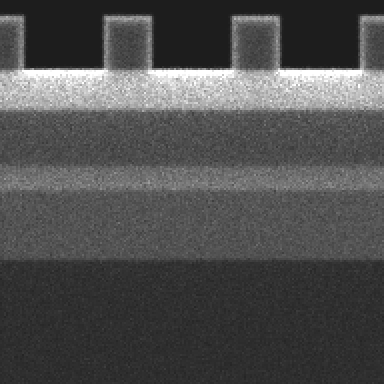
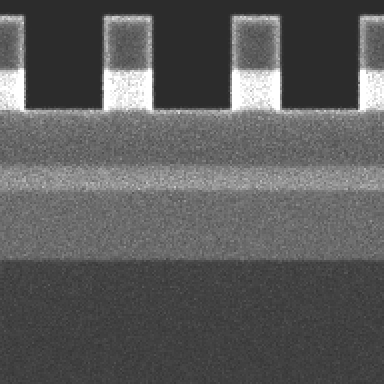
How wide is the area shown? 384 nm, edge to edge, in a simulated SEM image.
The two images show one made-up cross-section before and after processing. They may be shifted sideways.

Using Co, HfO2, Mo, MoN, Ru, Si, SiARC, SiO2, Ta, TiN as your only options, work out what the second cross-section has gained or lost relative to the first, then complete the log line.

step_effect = removed HfO2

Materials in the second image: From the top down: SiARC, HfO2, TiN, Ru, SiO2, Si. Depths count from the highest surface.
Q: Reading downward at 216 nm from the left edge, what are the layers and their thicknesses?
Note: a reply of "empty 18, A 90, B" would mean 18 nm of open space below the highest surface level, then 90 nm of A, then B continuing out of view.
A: empty 94, TiN 56, Ru 24, SiO2 70, Si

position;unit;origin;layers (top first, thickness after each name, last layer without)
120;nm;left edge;SiARC 54, HfO2 40, TiN 56, Ru 24, SiO2 70, Si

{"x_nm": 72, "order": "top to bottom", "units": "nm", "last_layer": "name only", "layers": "empty 94, TiN 56, Ru 24, SiO2 70, Si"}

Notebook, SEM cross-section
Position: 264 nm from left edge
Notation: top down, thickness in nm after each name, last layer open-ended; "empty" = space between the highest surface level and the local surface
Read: SiARC 54, HfO2 40, TiN 56, Ru 24, SiO2 70, Si